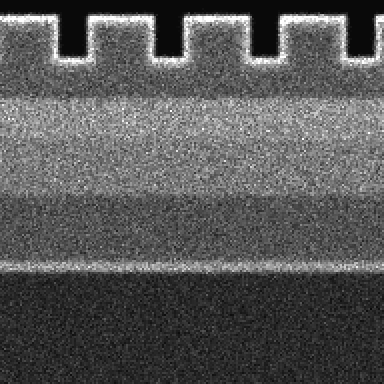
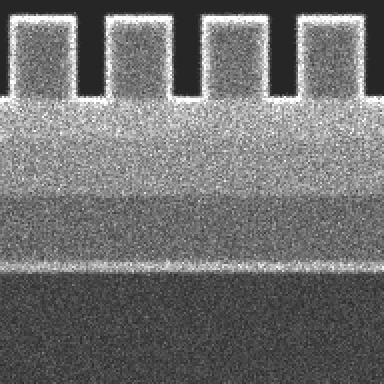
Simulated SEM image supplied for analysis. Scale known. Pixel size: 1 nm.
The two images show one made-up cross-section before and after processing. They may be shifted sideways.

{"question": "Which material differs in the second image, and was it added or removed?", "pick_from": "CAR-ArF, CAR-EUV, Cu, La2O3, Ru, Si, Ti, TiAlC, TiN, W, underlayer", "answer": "underlayer, removed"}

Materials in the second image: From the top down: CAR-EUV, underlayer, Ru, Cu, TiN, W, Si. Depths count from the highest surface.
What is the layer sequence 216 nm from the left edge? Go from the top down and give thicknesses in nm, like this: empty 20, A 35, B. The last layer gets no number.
CAR-EUV 42, underlayer 40, Ru 42, Cu 56, TiN 66, W 10, Si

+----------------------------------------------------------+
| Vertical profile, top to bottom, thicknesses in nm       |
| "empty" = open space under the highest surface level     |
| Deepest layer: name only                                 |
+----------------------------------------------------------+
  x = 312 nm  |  CAR-EUV 42, underlayer 40, Ru 42, Cu 56, TiN 66, W 10, Si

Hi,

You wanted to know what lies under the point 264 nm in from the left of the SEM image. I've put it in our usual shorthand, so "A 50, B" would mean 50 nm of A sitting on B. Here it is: CAR-EUV 42, underlayer 40, Ru 42, Cu 56, TiN 66, W 10, Si